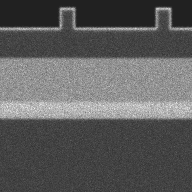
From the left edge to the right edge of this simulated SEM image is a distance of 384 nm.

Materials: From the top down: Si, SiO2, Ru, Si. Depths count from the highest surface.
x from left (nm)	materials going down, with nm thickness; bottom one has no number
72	empty 40, Si 60, SiO2 88, Ru 34, Si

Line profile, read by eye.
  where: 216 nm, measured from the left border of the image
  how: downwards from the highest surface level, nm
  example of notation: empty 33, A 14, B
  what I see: empty 40, Si 60, SiO2 88, Ru 34, Si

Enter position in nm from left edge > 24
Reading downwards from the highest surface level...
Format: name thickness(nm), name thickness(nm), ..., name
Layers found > empty 40, Si 60, SiO2 88, Ru 34, Si